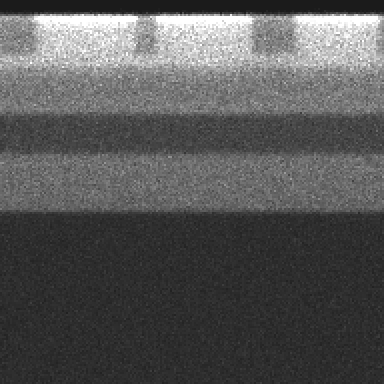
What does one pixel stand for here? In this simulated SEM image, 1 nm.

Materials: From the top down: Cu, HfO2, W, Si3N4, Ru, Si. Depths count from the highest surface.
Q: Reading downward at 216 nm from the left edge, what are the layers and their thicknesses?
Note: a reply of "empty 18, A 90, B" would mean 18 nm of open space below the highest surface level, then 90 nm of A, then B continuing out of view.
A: HfO2 50, W 48, Si3N4 40, Ru 58, Si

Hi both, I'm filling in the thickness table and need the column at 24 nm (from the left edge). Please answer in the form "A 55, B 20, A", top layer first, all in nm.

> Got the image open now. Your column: Cu 38, HfO2 12, W 48, Si3N4 40, Ru 58, Si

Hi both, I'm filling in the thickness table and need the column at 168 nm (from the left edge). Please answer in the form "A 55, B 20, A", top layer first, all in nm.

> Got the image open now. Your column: HfO2 50, W 48, Si3N4 40, Ru 58, Si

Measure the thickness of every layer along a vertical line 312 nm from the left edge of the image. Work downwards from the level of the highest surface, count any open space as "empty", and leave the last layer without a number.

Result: HfO2 50, W 48, Si3N4 40, Ru 58, Si